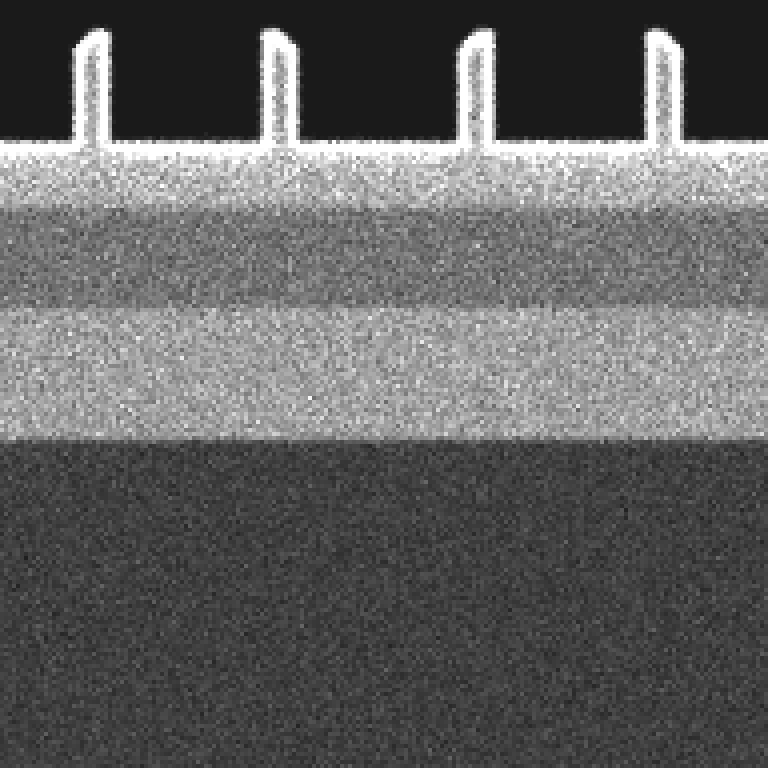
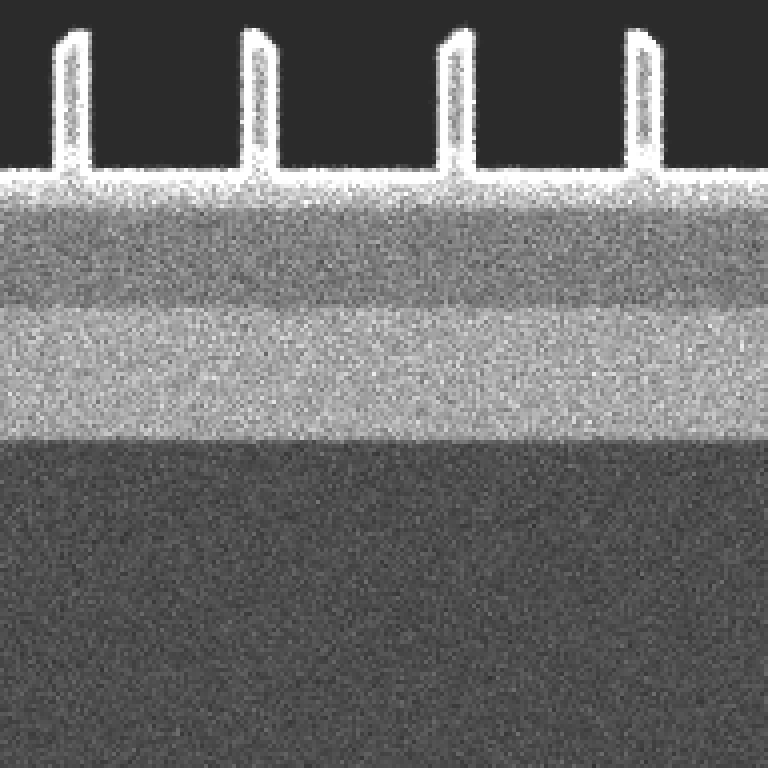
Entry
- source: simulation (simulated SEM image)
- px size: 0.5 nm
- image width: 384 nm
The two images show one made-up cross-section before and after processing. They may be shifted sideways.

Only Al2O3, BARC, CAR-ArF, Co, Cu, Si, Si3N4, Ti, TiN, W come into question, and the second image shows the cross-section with Co removed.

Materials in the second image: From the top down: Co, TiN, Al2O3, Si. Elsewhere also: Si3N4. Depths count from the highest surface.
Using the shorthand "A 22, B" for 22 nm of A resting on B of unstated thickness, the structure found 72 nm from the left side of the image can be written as empty 70, Co 18, TiN 50, Al2O3 66, Si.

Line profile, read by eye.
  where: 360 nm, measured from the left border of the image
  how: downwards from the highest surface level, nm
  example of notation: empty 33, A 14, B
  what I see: empty 70, Co 18, TiN 50, Al2O3 66, Si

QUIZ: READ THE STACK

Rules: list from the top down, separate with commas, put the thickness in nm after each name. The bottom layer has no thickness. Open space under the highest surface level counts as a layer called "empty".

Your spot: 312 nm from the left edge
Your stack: empty 70, Co 18, TiN 50, Al2O3 66, Si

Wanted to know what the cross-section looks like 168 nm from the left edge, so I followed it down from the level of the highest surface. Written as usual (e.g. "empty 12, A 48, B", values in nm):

empty 70, Co 18, TiN 50, Al2O3 66, Si